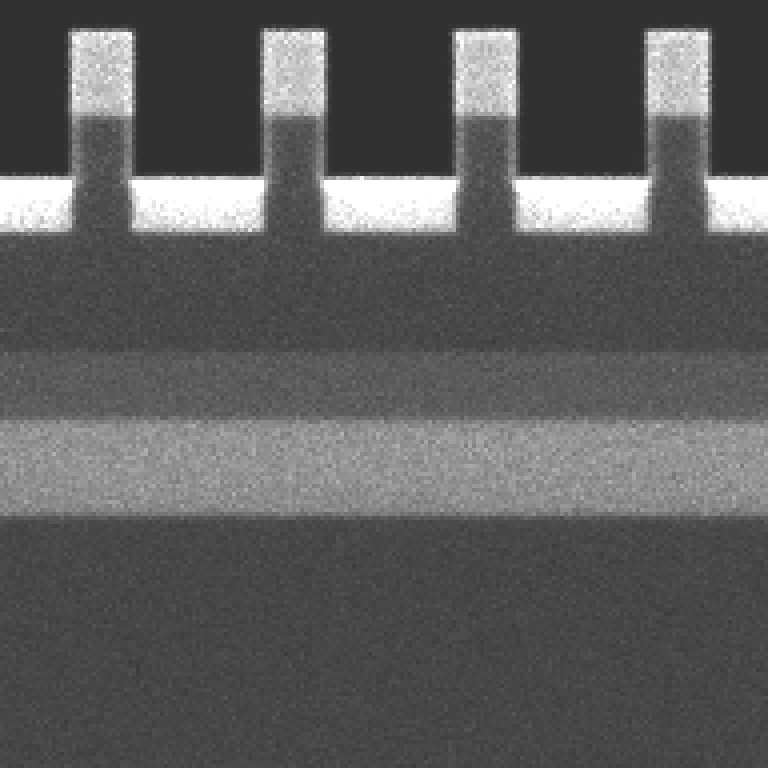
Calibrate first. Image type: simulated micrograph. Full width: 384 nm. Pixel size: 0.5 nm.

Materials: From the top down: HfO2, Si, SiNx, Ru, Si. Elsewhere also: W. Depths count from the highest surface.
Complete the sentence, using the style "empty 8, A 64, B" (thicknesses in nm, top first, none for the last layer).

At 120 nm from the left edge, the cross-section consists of empty 74, HfO2 26, Si 60, SiNx 34, Ru 48, Si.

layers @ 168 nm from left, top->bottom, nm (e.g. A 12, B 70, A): empty 74, HfO2 26, Si 60, SiNx 34, Ru 48, Si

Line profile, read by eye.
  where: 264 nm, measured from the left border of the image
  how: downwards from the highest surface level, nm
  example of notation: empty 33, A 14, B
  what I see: empty 74, HfO2 26, Si 60, SiNx 34, Ru 48, Si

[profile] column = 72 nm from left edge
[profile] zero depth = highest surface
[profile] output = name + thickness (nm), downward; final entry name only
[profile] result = empty 74, HfO2 26, Si 60, SiNx 34, Ru 48, Si